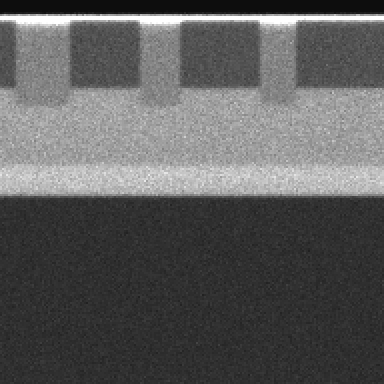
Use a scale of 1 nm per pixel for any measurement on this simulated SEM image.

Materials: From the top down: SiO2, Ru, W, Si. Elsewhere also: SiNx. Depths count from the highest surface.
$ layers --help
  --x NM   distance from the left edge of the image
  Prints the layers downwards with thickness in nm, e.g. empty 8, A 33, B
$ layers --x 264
SiO2 90, Ru 60, W 30, Si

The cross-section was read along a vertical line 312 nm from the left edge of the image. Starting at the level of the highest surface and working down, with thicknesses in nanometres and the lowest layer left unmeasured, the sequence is SiNx 72, Ru 78, W 30, Si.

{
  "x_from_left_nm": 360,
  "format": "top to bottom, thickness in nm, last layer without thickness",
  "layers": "SiNx 72, Ru 78, W 30, Si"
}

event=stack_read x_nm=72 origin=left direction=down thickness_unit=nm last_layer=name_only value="SiNx 72, Ru 78, W 30, Si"